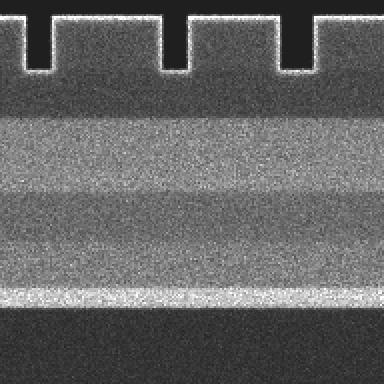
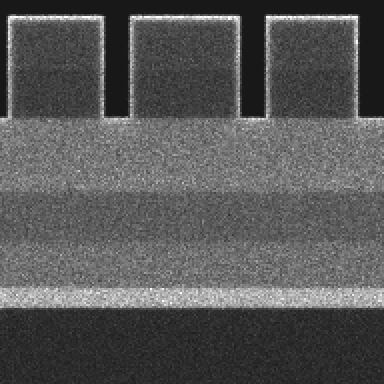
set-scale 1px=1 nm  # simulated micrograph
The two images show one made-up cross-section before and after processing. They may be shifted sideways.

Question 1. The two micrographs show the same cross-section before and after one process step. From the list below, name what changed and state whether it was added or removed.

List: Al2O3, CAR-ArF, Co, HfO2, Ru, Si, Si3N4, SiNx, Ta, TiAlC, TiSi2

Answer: SiNx, removed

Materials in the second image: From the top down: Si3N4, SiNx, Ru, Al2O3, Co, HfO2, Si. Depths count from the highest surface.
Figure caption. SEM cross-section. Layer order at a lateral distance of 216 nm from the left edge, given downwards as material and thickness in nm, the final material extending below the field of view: Si3N4 54, SiNx 48, Ru 74, Al2O3 50, Co 46, HfO2 20, Si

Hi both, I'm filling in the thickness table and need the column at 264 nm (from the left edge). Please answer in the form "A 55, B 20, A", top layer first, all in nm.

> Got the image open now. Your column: empty 102, Ru 74, Al2O3 50, Co 46, HfO2 20, Si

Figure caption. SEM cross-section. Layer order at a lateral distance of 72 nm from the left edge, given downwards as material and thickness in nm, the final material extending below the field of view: Si3N4 54, SiNx 48, Ru 74, Al2O3 50, Co 46, HfO2 20, Si